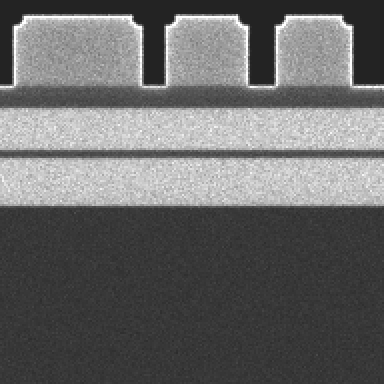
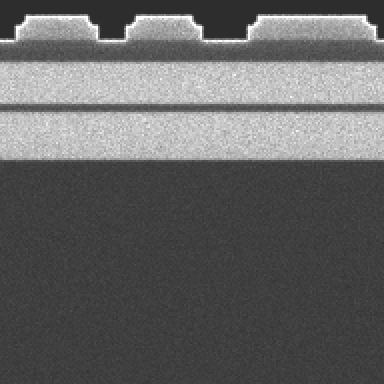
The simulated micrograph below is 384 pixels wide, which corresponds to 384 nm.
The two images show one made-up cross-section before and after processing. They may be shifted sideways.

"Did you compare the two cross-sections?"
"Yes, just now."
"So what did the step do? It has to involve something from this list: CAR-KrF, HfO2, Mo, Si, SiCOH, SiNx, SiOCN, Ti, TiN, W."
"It removed W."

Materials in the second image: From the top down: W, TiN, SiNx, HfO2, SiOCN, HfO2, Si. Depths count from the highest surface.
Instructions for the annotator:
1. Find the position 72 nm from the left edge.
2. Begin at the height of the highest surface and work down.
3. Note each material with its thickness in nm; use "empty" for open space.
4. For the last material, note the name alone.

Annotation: W 24, TiN 10, SiNx 12, HfO2 42, SiOCN 8, HfO2 48, Si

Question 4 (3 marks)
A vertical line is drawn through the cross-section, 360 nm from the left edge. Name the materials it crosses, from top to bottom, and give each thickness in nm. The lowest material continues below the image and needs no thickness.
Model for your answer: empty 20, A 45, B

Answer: W 24, TiN 10, SiNx 12, HfO2 42, SiOCN 8, HfO2 48, Si